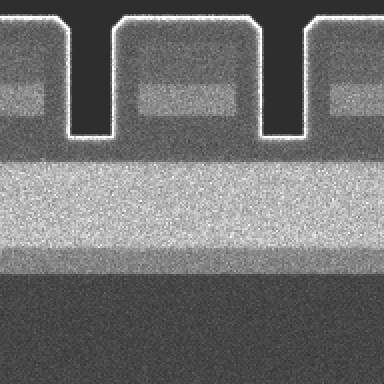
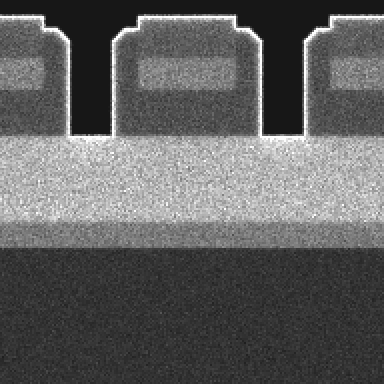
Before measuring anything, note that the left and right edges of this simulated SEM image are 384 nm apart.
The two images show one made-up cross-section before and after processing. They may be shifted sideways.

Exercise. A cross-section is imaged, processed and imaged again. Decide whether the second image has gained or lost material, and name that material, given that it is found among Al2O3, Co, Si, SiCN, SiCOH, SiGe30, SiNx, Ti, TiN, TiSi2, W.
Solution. removed: SiNx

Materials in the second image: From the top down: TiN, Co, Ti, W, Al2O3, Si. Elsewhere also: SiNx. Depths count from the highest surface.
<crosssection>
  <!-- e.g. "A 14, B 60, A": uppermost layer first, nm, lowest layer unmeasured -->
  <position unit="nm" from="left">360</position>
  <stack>TiN 42, Co 32, Ti 46, W 86, Al2O3 26, Si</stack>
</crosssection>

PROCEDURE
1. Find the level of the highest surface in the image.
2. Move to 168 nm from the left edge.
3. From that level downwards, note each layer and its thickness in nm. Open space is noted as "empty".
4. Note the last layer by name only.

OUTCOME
TiN 42, Co 32, Ti 46, W 86, Al2O3 26, Si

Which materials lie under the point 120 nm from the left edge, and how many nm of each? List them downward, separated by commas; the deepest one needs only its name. empty 16, SiNx 104, W 86, Al2O3 26, Si